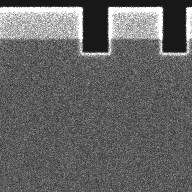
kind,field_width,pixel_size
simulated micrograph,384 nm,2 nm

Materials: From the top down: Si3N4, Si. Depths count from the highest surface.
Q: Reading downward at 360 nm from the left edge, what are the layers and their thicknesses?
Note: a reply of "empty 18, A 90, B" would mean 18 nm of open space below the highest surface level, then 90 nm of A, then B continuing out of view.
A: empty 90, Si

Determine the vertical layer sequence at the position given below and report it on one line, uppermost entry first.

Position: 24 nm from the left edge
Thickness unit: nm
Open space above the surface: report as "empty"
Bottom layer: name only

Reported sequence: Si3N4 62, Si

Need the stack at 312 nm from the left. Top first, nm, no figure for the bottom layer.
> Si3N4 62, Si